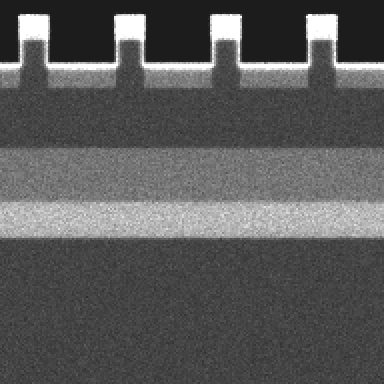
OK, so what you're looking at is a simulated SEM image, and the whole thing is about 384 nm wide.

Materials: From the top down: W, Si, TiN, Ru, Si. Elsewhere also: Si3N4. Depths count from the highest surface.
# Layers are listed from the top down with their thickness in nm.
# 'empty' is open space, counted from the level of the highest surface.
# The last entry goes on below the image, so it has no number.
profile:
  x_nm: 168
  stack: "empty 48, Si3N4 24, Si 60, TiN 54, Ru 36, Si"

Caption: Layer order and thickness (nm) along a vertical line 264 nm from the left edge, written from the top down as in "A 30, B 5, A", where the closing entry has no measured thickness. empty 48, Si3N4 24, Si 60, TiN 54, Ru 36, Si